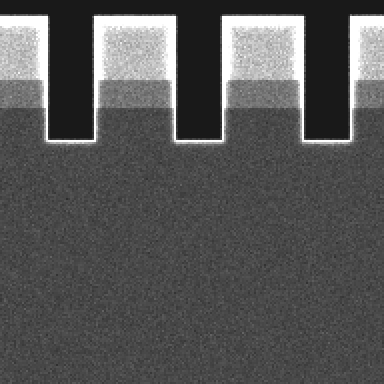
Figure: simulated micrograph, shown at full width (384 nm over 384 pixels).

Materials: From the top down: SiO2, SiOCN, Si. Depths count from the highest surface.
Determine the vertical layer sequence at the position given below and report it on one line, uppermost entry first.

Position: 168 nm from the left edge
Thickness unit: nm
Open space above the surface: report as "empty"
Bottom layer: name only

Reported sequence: SiO2 64, SiOCN 28, Si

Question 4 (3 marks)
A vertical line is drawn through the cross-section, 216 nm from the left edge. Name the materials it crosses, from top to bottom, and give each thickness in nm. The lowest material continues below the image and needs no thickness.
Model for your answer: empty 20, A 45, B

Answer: empty 124, Si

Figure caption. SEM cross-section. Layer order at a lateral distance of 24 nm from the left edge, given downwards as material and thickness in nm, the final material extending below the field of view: SiO2 64, SiOCN 28, Si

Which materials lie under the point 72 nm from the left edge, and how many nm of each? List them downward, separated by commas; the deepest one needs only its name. empty 124, Si